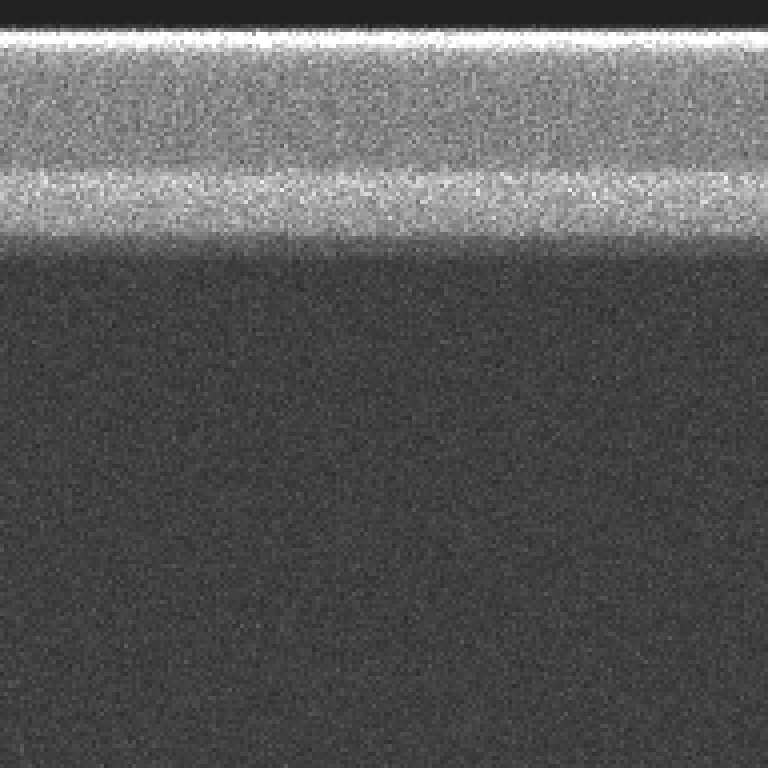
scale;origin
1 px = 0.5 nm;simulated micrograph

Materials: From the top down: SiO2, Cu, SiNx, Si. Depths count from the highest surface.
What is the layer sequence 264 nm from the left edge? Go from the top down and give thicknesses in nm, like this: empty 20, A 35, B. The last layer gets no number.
SiO2 70, Cu 32, SiNx 10, Si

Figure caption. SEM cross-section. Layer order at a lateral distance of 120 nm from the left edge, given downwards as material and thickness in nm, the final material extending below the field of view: SiO2 70, Cu 32, SiNx 10, Si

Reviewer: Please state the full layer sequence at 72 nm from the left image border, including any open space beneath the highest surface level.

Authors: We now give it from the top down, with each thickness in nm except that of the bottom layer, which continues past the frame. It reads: SiO2 70, Cu 32, SiNx 10, Si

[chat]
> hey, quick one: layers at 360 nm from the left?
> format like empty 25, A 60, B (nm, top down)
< SiO2 70, Cu 32, SiNx 10, Si